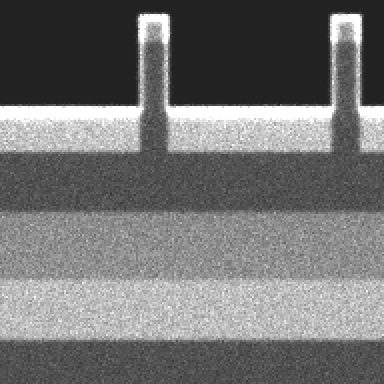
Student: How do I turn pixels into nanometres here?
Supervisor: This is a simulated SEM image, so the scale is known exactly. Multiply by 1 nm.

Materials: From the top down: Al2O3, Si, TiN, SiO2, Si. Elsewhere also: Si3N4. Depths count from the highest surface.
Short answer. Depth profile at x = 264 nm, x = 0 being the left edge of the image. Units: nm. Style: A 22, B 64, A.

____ empty 92, Al2O3 44, Si 60, TiN 68, SiO2 60, Si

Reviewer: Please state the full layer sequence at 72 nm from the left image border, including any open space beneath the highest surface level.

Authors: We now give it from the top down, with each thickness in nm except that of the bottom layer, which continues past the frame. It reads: empty 92, Al2O3 44, Si 60, TiN 68, SiO2 60, Si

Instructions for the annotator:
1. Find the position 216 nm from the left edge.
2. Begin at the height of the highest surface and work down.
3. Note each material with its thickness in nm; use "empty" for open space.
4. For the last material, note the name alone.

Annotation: empty 92, Al2O3 44, Si 60, TiN 68, SiO2 60, Si